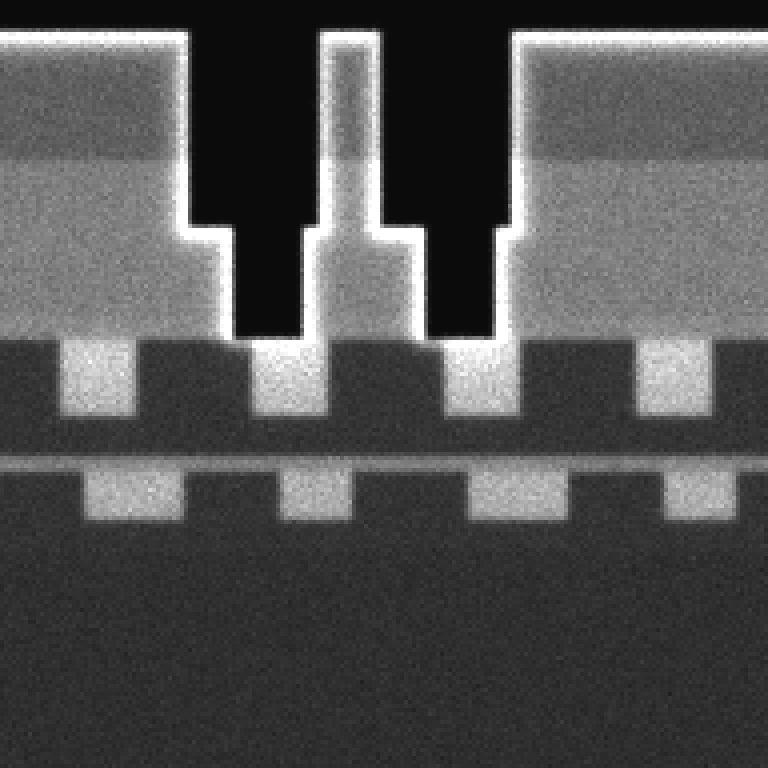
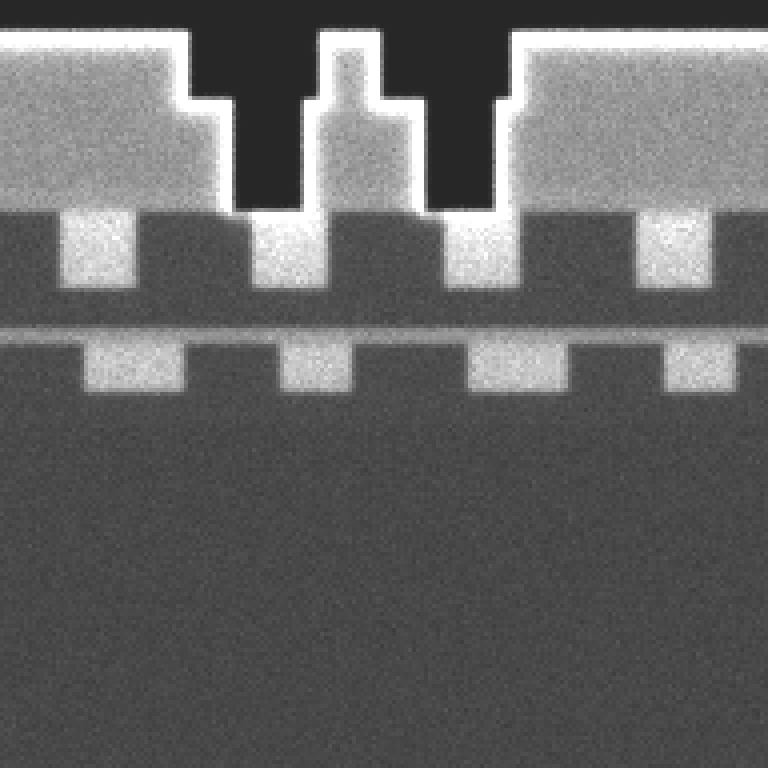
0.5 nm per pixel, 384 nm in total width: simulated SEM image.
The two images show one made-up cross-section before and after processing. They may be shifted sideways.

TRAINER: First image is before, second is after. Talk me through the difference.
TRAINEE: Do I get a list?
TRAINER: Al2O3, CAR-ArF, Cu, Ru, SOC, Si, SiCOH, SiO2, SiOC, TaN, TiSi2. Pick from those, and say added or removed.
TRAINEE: removed: SOC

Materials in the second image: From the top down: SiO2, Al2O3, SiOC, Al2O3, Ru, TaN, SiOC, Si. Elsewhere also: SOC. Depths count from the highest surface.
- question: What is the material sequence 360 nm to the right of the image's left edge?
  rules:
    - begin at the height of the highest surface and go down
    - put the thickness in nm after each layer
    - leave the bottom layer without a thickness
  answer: SiO2 78, Al2O3 12, SiOC 58, Al2O3 8, TaN 24, SiOC 16, Si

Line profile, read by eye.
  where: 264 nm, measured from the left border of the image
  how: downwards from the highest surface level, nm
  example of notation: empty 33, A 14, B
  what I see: SiO2 78, Al2O3 12, SiOC 58, Al2O3 8, Ru 16, TaN 8, SiOC 16, Si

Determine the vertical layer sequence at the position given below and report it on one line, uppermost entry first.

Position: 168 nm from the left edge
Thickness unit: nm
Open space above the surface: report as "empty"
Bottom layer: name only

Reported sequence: SiO2 78, Al2O3 12, SiOC 58, Al2O3 8, TaN 24, SiOC 16, Si